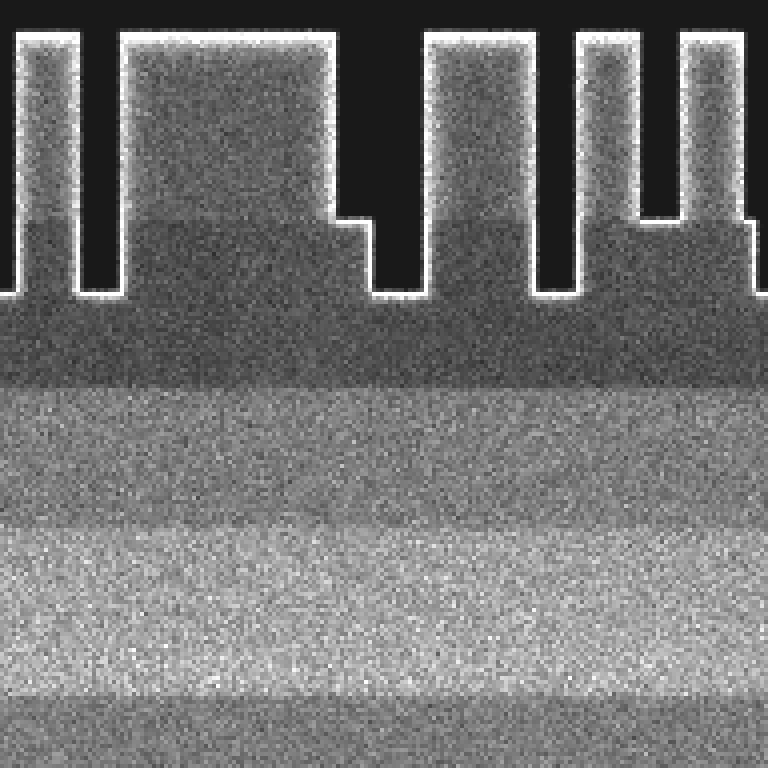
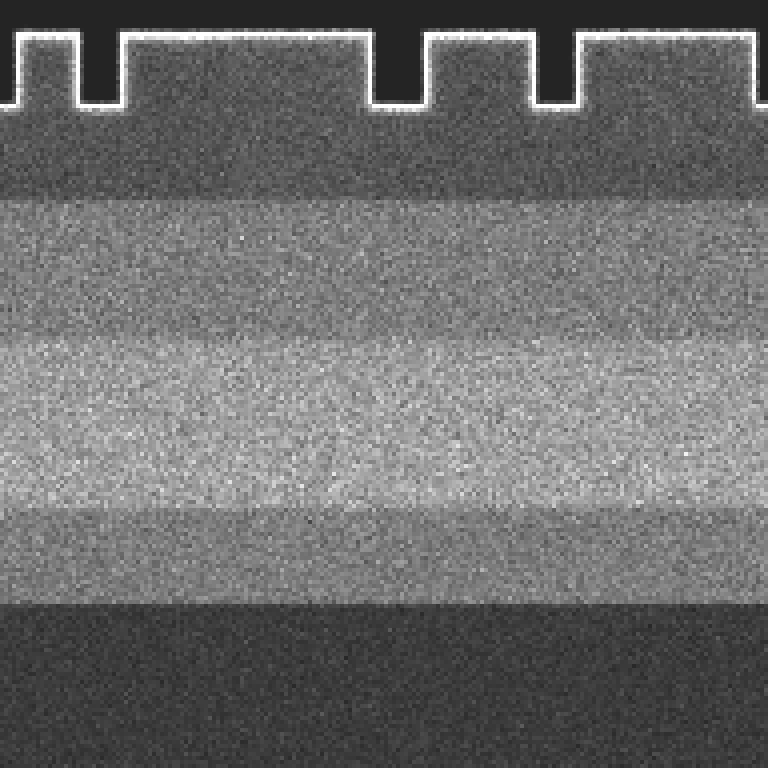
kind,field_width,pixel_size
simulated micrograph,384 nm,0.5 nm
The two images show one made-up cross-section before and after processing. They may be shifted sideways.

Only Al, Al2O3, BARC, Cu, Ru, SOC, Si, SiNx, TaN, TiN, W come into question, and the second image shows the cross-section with SOC removed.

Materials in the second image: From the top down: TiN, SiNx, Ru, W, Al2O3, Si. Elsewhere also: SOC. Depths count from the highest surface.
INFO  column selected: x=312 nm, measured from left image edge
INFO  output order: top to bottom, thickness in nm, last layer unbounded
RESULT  TiN 58, SiNx 26, Ru 70, W 84, Al2O3 48, Si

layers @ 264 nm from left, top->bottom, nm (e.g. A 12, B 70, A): SiNx 84, Ru 70, W 84, Al2O3 48, Si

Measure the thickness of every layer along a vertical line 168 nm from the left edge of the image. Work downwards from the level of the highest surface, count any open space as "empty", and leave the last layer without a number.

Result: TiN 84, Ru 70, W 84, Al2O3 48, Si